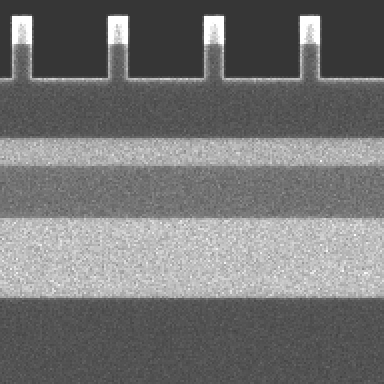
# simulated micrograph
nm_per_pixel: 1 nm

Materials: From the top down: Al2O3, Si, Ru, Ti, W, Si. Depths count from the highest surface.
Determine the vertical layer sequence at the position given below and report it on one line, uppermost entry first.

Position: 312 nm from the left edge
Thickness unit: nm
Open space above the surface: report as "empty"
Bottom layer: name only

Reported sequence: Al2O3 28, Si 94, Ru 28, Ti 52, W 80, Si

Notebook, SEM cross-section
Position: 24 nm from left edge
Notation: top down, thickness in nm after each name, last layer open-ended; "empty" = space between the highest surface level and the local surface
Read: Al2O3 28, Si 94, Ru 28, Ti 52, W 80, Si